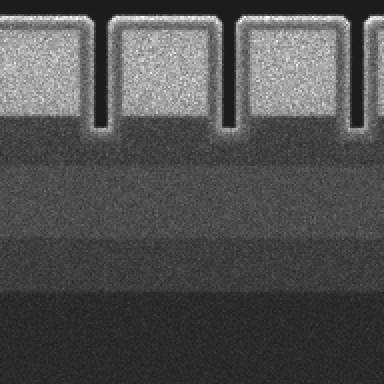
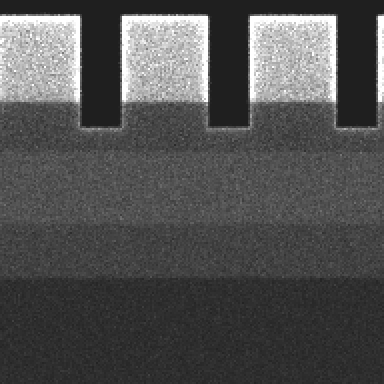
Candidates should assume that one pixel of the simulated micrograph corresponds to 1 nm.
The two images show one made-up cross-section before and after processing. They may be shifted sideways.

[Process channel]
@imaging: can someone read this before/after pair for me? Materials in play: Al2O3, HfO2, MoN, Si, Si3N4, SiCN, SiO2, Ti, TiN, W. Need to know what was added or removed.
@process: Al2O3 removed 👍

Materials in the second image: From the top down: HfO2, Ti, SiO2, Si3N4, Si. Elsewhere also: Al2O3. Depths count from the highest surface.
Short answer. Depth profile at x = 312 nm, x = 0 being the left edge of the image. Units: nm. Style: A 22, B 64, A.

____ HfO2 86, Ti 50, SiO2 72, Si3N4 54, Si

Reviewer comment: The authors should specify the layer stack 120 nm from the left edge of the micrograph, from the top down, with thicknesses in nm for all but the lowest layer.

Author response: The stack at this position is empty 112, Ti 24, SiO2 72, Si3N4 54, Si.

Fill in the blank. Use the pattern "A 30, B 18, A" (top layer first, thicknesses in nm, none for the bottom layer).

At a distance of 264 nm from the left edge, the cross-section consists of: HfO2 86, Ti 50, SiO2 72, Si3N4 54, Si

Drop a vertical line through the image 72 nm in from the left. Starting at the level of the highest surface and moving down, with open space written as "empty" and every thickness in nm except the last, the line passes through HfO2 86, Ti 50, SiO2 72, Si3N4 54, Si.